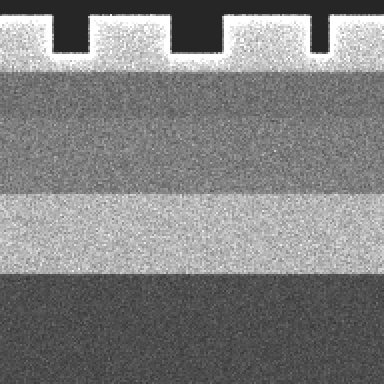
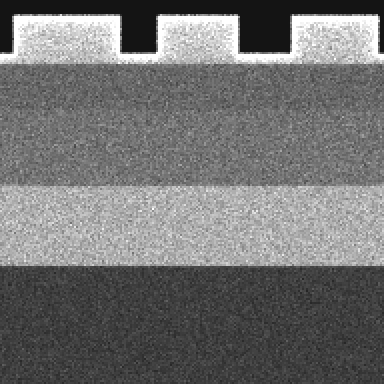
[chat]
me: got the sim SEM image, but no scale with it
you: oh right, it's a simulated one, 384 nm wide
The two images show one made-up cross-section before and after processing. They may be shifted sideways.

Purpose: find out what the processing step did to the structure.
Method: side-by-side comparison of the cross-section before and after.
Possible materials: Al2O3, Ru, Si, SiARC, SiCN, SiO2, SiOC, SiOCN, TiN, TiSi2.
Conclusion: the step removed Ru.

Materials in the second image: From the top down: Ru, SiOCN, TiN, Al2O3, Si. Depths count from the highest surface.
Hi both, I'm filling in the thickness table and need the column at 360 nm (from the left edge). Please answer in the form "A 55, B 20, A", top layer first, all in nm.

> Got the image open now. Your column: Ru 48, SiOCN 46, TiN 76, Al2O3 80, Si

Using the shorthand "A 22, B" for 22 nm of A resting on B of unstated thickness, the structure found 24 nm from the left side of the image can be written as Ru 48, SiOCN 46, TiN 76, Al2O3 80, Si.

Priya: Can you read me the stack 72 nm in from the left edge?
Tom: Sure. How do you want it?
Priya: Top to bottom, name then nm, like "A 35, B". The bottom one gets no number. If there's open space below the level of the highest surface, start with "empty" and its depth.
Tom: Ru 48, SiOCN 46, TiN 76, Al2O3 80, Si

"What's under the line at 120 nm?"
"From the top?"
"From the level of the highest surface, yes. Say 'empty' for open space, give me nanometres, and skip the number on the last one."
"empty 38, Ru 10, SiOCN 46, TiN 76, Al2O3 80, Si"